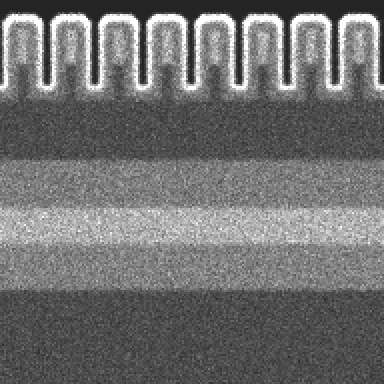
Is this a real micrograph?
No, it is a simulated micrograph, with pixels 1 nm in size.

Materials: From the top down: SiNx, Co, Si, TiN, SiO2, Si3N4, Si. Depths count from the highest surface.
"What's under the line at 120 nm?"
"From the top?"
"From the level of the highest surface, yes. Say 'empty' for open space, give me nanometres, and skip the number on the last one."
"SiNx 14, Co 34, Si 96, TiN 48, SiO2 36, Si3N4 46, Si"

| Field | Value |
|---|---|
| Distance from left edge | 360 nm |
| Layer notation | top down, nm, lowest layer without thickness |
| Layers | SiNx 14, Co 34, Si 96, TiN 48, SiO2 36, Si3N4 46, Si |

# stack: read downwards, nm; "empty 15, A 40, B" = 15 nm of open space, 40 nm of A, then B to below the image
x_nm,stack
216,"SiNx 14, Co 34, Si 96, TiN 48, SiO2 36, Si3N4 46, Si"